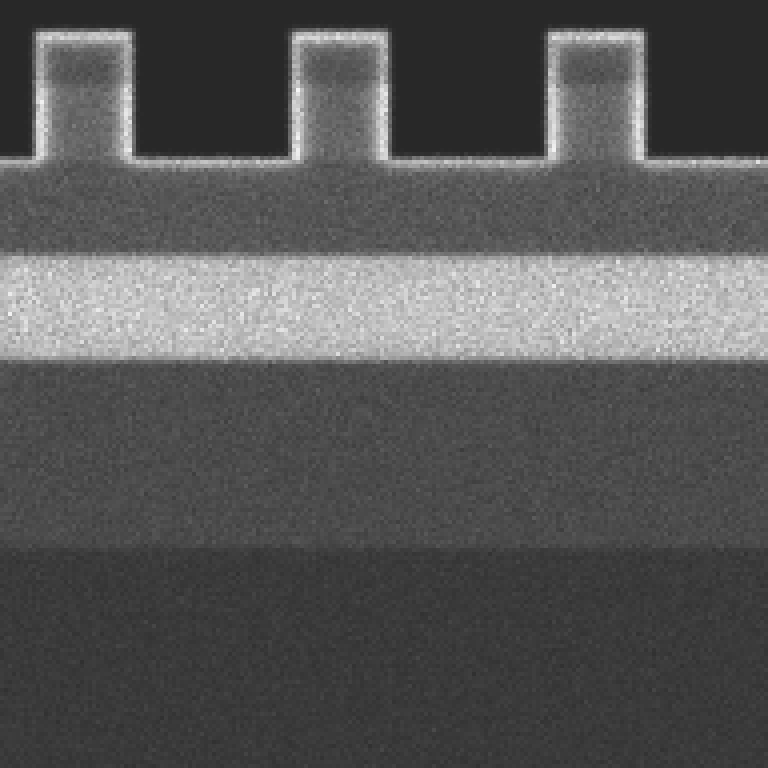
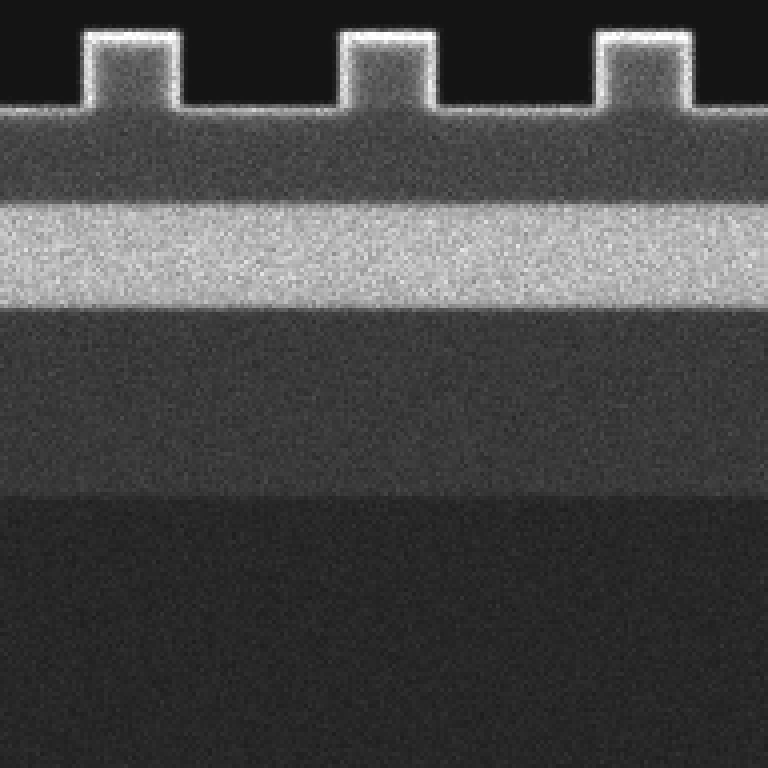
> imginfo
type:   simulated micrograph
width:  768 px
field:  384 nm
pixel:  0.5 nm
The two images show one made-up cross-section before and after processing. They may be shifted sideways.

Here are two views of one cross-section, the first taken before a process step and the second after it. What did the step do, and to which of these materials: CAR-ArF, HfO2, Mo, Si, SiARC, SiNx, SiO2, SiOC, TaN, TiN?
It removed SiARC.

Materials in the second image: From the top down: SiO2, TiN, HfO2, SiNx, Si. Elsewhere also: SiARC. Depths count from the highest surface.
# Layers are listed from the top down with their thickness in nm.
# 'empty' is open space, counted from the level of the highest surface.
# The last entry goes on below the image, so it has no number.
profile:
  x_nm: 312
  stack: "SiO2 38, TiN 48, HfO2 52, SiNx 94, Si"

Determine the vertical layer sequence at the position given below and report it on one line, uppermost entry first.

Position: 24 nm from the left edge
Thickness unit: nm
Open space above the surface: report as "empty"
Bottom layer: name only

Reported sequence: empty 38, TiN 48, HfO2 52, SiNx 94, Si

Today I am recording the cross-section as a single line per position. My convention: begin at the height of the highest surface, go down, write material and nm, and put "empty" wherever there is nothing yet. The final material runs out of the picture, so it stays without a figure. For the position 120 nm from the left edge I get empty 38, TiN 48, HfO2 52, SiNx 94, Si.